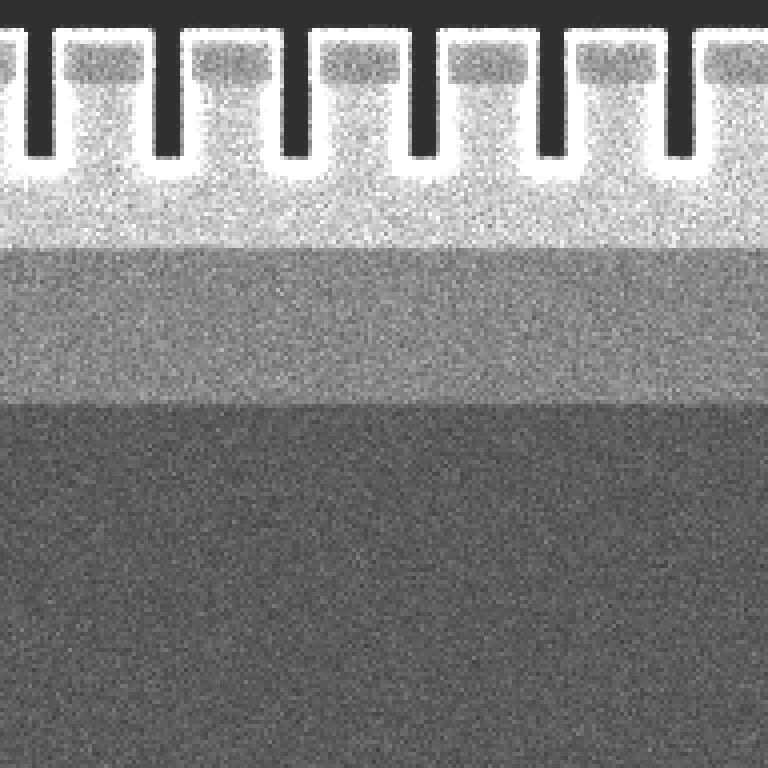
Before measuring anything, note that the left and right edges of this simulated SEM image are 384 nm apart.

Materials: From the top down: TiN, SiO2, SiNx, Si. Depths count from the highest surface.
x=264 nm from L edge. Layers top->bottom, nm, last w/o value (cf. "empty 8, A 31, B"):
TiN 26, SiO2 82, SiNx 78, Si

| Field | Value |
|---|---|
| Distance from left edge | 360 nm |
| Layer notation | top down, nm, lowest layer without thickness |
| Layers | TiN 26, SiO2 82, SiNx 78, Si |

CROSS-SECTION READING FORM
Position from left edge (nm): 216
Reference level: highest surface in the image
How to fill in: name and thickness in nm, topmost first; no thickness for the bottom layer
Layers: empty 64, SiO2 44, SiNx 78, Si